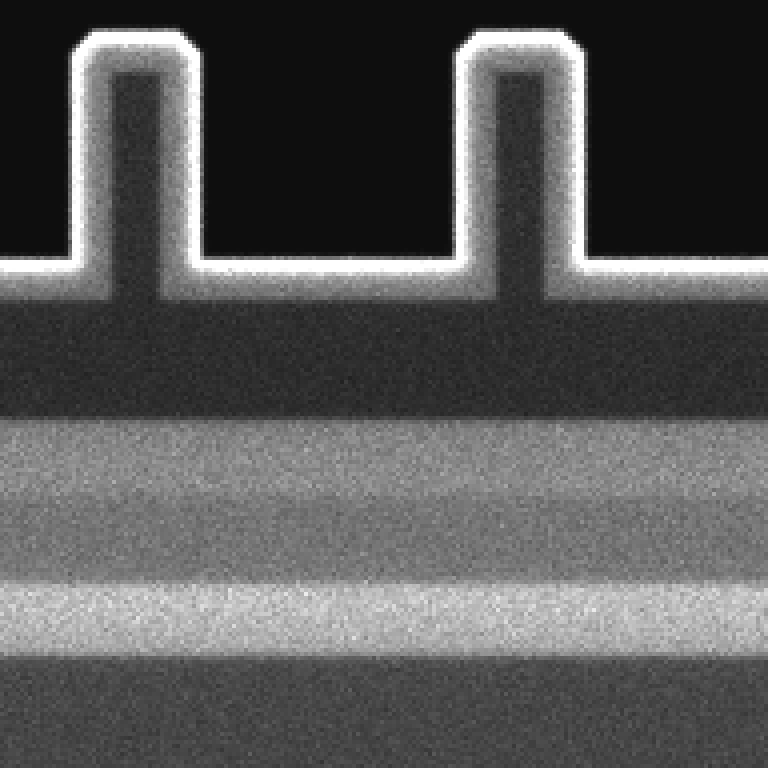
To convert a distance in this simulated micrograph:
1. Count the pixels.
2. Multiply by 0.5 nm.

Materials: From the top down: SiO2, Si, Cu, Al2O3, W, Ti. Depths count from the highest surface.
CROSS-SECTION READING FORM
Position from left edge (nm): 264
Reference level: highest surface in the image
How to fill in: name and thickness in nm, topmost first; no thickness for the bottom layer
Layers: SiO2 20, Si 174, Cu 38, Al2O3 44, W 36, Ti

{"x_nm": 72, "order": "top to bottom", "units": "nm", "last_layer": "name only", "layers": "SiO2 20, Si 174, Cu 38, Al2O3 44, W 36, Ti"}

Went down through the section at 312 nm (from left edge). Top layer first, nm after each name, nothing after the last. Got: empty 114, SiO2 20, Si 60, Cu 38, Al2O3 44, W 36, Ti